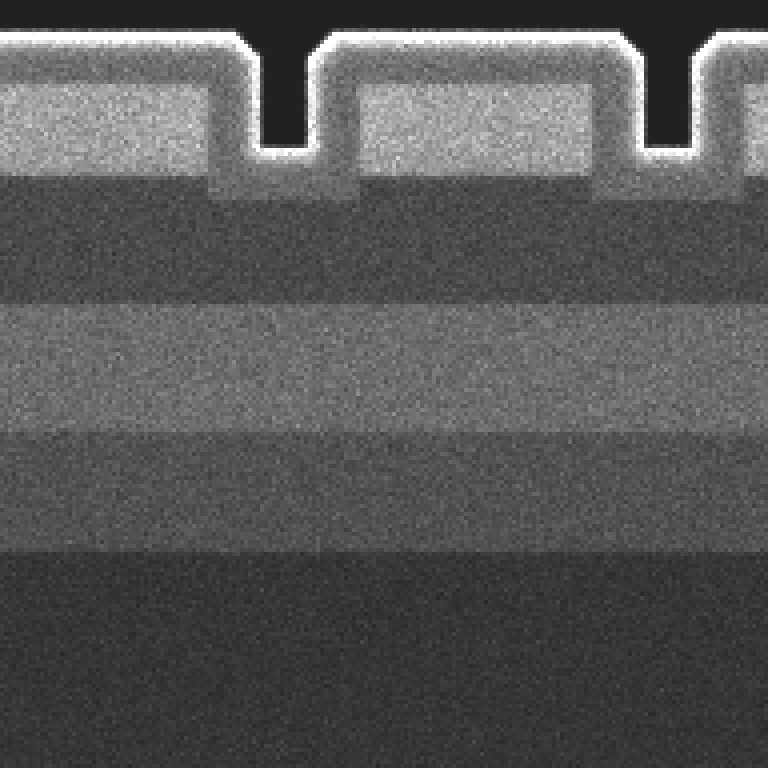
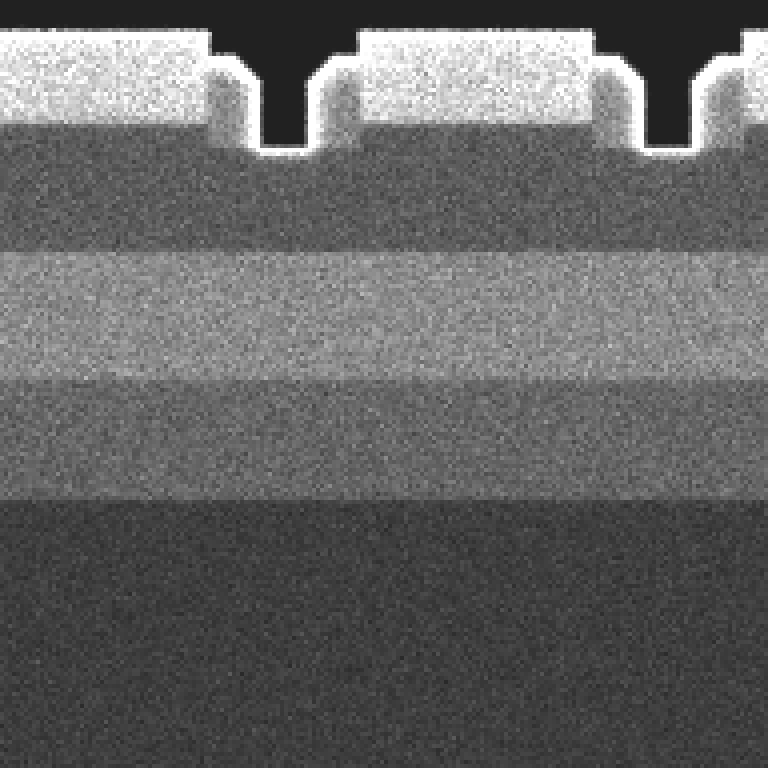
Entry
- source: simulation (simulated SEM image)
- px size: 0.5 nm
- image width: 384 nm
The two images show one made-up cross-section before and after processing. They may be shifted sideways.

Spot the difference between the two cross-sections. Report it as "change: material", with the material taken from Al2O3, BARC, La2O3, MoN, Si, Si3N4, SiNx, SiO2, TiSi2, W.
removed: SiO2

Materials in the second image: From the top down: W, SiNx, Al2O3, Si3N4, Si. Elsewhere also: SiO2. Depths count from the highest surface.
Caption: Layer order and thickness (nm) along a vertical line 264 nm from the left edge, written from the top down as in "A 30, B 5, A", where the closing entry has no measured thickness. W 46, SiNx 64, Al2O3 64, Si3N4 60, Si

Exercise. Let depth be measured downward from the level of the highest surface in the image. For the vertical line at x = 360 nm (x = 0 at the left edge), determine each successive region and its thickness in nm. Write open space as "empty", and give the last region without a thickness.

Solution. empty 12, SiO2 46, SiNx 52, Al2O3 64, Si3N4 60, Si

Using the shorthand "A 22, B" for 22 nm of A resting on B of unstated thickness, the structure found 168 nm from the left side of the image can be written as empty 12, SiO2 46, SiNx 52, Al2O3 64, Si3N4 60, Si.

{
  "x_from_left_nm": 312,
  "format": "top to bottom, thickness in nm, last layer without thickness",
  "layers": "empty 16, SiO2 42, SiNx 52, Al2O3 64, Si3N4 60, Si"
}